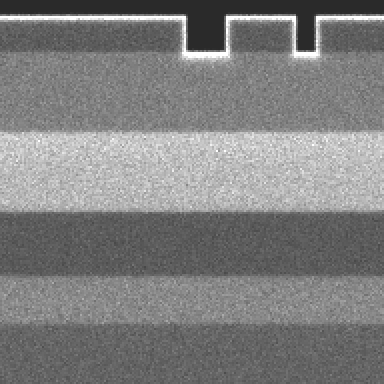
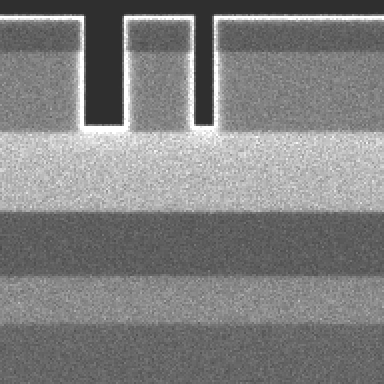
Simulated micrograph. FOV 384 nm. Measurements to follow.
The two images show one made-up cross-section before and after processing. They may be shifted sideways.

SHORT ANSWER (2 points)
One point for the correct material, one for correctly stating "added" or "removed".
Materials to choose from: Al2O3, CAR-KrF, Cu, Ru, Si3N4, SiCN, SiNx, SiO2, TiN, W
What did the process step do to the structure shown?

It removed SiO2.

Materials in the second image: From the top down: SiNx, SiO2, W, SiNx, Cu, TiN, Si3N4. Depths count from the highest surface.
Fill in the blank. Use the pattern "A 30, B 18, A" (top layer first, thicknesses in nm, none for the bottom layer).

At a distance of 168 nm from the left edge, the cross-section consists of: SiNx 36, SiO2 80, W 80, SiNx 64, Cu 48, TiN 30, Si3N4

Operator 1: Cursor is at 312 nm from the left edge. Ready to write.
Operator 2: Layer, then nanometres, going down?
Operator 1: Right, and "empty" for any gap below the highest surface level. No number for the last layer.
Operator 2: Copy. SiNx 36, SiO2 80, W 80, SiNx 64, Cu 48, TiN 30, Si3N4